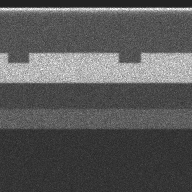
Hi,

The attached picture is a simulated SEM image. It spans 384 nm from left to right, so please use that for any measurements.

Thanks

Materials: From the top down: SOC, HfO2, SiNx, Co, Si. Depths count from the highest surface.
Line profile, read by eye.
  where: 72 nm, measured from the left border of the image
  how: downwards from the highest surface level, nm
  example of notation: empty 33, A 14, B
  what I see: SOC 90, HfO2 60, SiNx 52, Co 40, Si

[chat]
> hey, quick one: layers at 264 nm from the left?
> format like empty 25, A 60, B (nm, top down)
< SOC 110, HfO2 40, SiNx 52, Co 40, Si